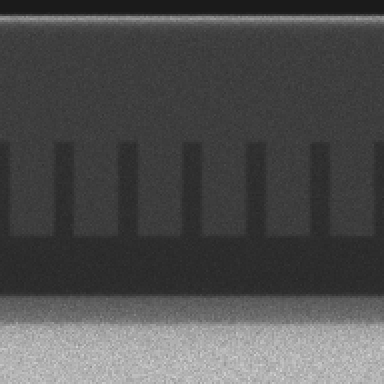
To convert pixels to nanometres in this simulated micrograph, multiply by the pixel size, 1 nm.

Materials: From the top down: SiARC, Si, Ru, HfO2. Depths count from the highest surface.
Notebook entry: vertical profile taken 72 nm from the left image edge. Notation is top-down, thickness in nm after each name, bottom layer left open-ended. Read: SiARC 126, Si 154, Ru 28, HfO2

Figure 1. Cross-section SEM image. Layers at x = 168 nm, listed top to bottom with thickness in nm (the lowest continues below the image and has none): SiARC 220, Si 60, Ru 28, HfO2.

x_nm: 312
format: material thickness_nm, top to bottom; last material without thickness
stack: SiARC 126, Si 154, Ru 28, HfO2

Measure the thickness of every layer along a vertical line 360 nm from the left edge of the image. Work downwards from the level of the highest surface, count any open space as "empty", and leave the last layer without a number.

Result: SiARC 220, Si 60, Ru 28, HfO2